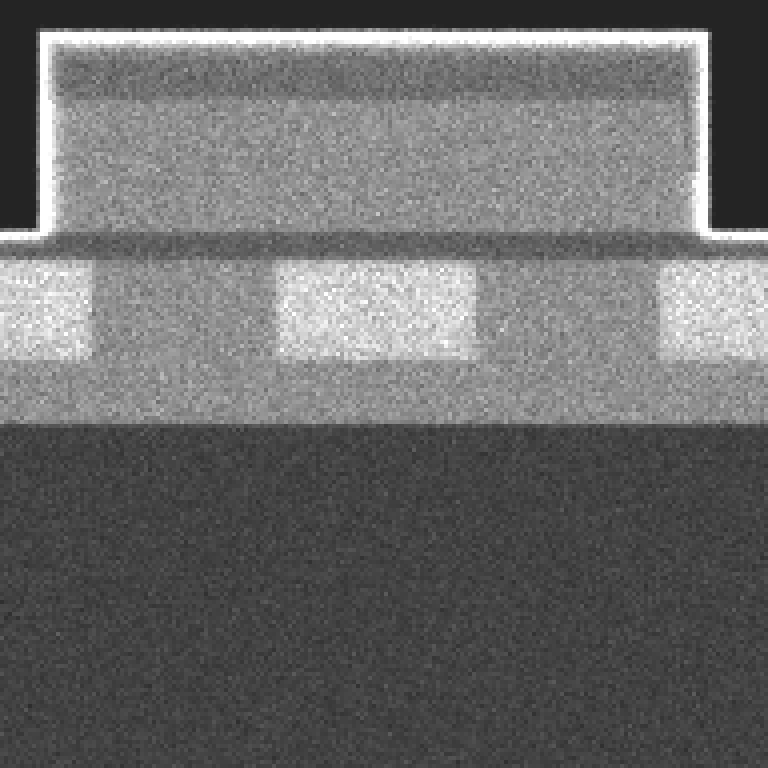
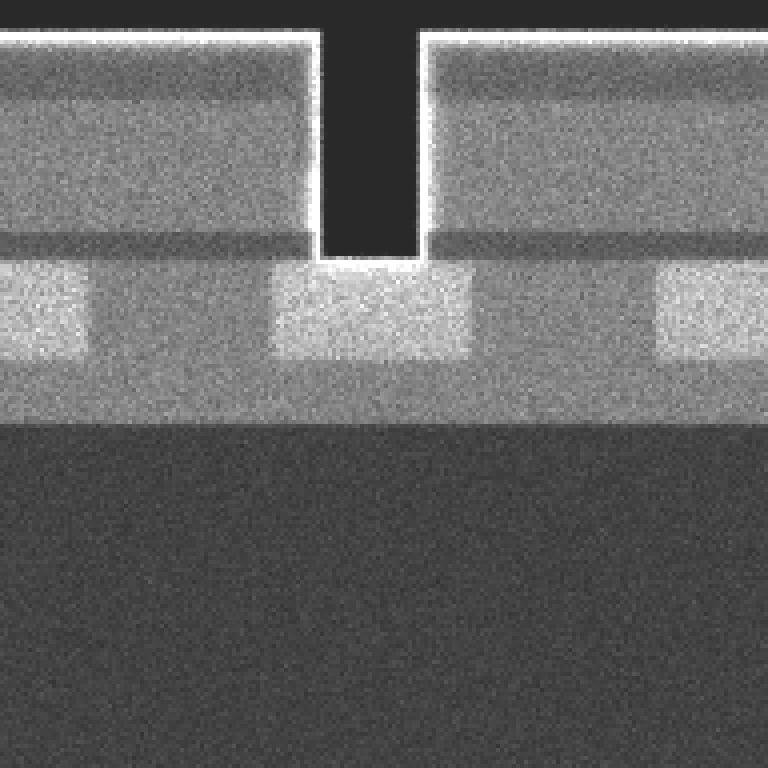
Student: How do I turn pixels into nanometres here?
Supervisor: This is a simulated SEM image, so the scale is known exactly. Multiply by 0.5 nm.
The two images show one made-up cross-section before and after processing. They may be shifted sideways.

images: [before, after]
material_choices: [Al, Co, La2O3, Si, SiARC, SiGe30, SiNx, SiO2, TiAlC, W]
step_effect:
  removed: SiNx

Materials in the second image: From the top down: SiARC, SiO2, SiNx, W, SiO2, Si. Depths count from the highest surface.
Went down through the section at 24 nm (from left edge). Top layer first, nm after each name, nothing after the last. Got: SiARC 34, SiO2 66, SiNx 14, W 50, SiO2 32, Si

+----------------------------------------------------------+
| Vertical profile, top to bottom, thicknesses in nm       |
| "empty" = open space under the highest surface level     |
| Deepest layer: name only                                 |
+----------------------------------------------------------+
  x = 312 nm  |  SiARC 34, SiO2 66, SiNx 14, SiO2 82, Si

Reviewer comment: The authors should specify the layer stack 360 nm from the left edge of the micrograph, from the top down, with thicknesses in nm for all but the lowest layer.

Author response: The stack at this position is SiARC 34, SiO2 66, SiNx 14, W 50, SiO2 32, Si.